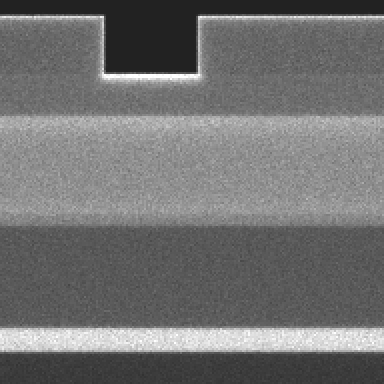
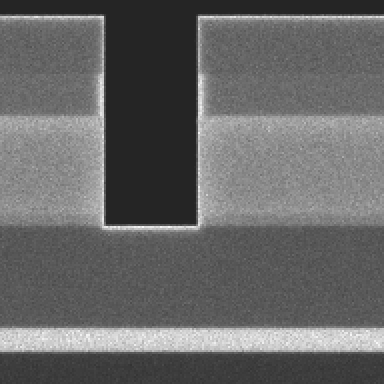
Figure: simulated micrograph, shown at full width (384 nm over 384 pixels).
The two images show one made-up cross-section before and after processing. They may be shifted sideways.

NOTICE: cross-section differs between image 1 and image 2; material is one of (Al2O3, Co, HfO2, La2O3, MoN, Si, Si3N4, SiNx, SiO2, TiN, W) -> removed: Co and SiO2 and W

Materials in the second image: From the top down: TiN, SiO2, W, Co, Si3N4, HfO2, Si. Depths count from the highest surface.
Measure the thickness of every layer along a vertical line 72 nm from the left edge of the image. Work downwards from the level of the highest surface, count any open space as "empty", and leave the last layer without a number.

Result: TiN 58, SiO2 42, W 98, Co 12, Si3N4 102, HfO2 24, Si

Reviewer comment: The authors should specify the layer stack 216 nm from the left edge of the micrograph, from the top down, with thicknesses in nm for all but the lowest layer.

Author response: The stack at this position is TiN 58, SiO2 42, W 98, Co 12, Si3N4 102, HfO2 24, Si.